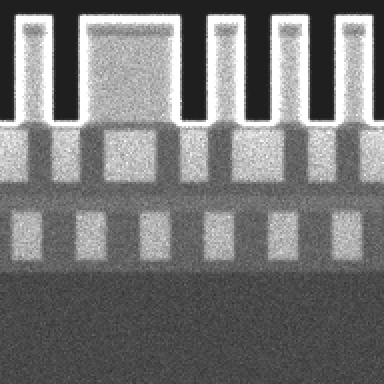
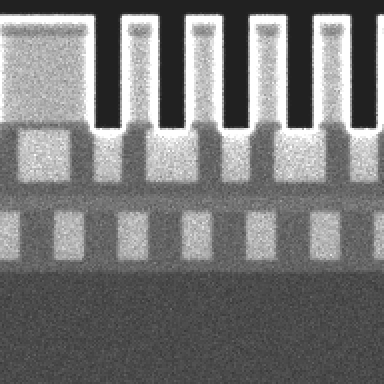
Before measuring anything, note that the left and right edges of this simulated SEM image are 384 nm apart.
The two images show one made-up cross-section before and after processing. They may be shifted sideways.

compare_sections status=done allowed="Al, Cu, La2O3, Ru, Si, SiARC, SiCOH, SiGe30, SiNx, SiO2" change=removed material="SiNx"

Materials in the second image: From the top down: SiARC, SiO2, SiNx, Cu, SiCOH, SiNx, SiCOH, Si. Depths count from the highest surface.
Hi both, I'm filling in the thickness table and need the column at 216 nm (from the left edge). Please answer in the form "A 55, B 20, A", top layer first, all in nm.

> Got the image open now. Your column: SiARC 20, SiO2 86, SiNx 8, SiCOH 66, SiNx 16, SiCOH 60, Si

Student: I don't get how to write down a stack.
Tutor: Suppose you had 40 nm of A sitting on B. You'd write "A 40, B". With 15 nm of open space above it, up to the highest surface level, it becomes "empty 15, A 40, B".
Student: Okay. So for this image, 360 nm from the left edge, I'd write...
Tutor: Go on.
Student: empty 114, Cu 52, SiCOH 14, SiNx 16, SiCOH 60, Si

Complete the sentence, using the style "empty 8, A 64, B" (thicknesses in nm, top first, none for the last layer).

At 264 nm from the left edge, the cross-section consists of SiARC 20, SiO2 86, SiNx 8, SiCOH 66, SiNx 16, Cu 48, SiCOH 12, Si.